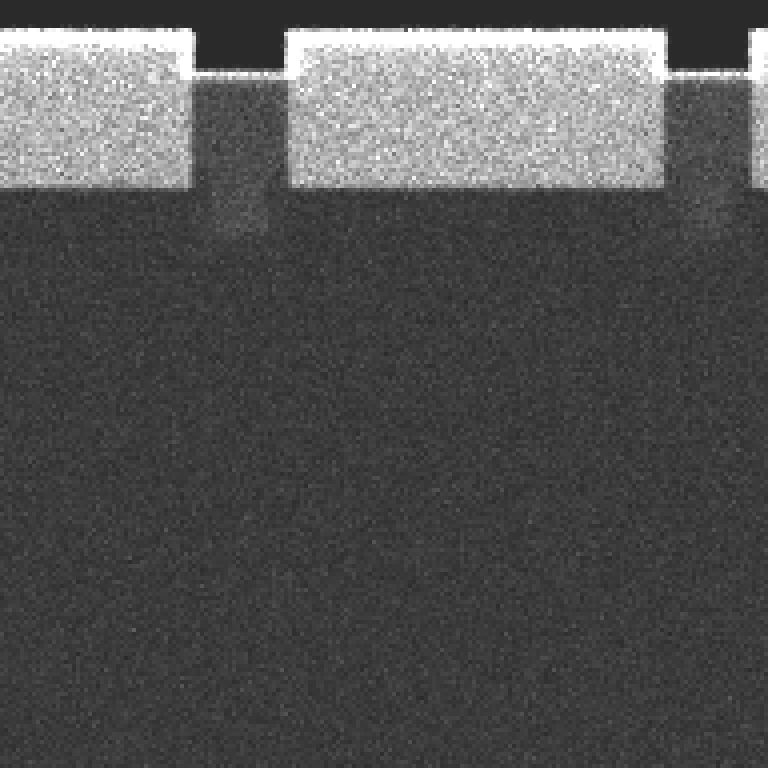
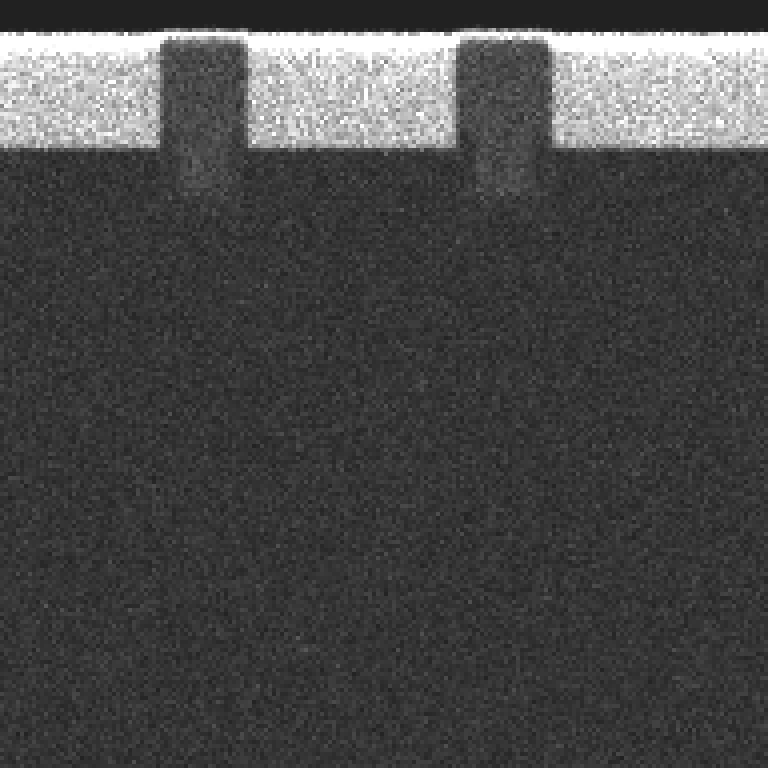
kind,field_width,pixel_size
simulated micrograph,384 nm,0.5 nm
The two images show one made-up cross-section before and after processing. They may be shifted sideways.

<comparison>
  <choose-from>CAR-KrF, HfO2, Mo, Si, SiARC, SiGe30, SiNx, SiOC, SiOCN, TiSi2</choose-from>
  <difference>HfO2 removed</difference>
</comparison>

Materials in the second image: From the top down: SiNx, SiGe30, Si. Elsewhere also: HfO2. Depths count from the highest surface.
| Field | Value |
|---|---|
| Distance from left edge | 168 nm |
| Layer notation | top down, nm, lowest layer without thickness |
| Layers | empty 2, HfO2 56, Si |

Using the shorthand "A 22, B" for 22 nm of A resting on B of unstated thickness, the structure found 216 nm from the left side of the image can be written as empty 2, HfO2 56, Si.